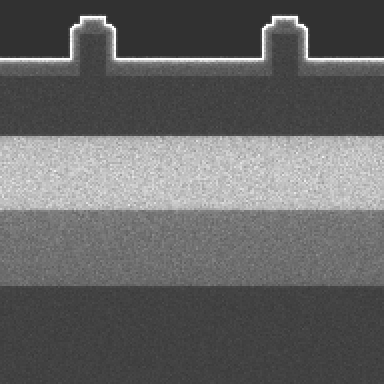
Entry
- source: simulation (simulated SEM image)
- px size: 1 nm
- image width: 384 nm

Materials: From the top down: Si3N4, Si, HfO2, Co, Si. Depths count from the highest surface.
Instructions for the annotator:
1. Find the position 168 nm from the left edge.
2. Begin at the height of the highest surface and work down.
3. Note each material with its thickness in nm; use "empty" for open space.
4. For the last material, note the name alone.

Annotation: empty 42, Si3N4 18, Si 60, HfO2 74, Co 76, Si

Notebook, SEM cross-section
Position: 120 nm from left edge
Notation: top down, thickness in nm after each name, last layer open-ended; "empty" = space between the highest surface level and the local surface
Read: empty 42, Si3N4 18, Si 60, HfO2 74, Co 76, Si